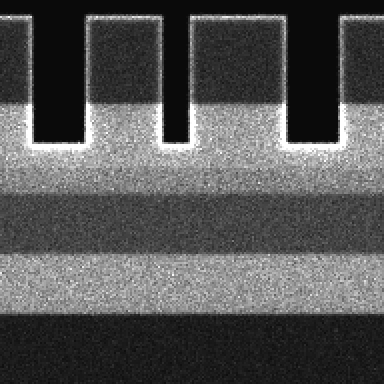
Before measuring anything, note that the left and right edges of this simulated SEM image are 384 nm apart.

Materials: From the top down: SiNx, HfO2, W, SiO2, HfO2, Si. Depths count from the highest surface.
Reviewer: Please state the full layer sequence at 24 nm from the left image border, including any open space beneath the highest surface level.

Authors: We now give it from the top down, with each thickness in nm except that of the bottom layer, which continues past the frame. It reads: SiNx 88, HfO2 64, W 26, SiO2 60, HfO2 60, Si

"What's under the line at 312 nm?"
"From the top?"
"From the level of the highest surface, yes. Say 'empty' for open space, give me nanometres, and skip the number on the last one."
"empty 128, HfO2 24, W 26, SiO2 60, HfO2 60, Si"